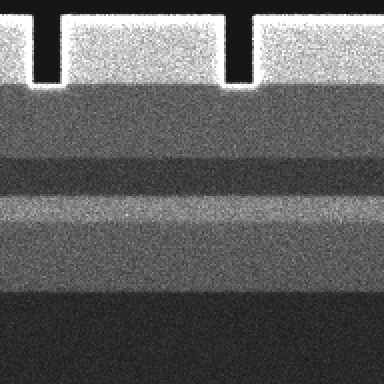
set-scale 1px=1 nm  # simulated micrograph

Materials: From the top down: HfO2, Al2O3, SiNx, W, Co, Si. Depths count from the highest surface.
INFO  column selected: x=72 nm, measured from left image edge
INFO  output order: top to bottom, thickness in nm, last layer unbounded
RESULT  HfO2 68, Al2O3 74, SiNx 38, W 26, Co 70, Si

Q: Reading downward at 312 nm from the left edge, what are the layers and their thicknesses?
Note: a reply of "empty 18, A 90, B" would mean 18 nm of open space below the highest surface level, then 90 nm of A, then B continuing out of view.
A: HfO2 68, Al2O3 74, SiNx 38, W 26, Co 70, Si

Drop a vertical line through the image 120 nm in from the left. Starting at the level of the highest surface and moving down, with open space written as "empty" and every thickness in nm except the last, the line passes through HfO2 68, Al2O3 74, SiNx 38, W 26, Co 70, Si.